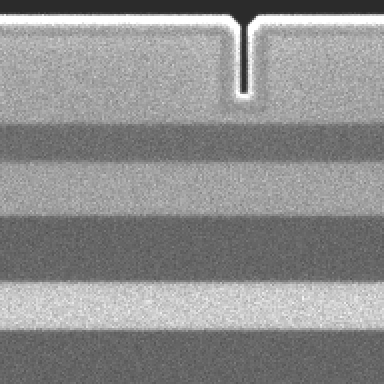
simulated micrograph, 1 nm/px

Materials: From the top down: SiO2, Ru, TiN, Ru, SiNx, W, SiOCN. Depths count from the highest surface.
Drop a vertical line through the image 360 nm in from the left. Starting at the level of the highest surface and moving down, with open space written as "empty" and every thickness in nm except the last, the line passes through SiO2 20, Ru 88, TiN 38, Ru 54, SiNx 66, W 48, SiOCN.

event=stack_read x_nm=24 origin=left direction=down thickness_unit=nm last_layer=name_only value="SiO2 20, Ru 88, TiN 38, Ru 54, SiNx 66, W 48, SiOCN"